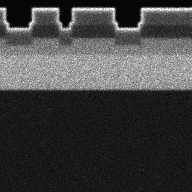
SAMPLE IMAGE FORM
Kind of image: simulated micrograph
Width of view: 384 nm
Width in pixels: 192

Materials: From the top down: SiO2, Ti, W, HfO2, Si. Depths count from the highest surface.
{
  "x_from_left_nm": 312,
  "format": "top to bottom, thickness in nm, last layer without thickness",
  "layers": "SiO2 34, Ti 26, W 34, HfO2 70, Si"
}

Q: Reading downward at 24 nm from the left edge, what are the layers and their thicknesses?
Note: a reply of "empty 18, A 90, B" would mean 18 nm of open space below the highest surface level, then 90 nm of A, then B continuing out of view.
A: empty 40, SiO2 34, W 20, HfO2 70, Si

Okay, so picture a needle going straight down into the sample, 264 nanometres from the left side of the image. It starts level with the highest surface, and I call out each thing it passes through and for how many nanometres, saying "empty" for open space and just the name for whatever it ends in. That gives empty 40, SiO2 34, W 20, HfO2 70, Si